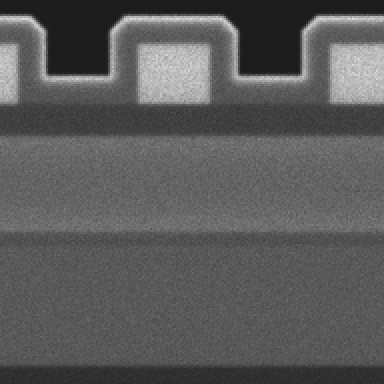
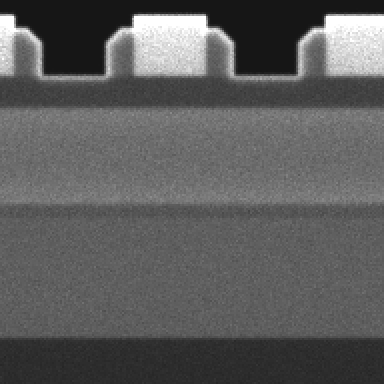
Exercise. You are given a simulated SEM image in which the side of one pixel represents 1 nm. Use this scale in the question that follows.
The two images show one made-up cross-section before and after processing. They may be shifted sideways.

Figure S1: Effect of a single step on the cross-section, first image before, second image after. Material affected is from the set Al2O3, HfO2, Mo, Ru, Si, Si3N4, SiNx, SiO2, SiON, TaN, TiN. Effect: removed SiO2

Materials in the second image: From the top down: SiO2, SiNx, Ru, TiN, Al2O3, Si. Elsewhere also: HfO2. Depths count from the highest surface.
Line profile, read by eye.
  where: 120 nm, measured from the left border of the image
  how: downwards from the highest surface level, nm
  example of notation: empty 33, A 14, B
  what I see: empty 12, SiO2 48, SiNx 32, Ru 96, TiN 14, Al2O3 120, Si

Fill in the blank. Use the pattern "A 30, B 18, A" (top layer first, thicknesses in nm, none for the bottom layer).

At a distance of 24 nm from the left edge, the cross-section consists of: empty 12, SiO2 48, SiNx 32, Ru 96, TiN 14, Al2O3 120, Si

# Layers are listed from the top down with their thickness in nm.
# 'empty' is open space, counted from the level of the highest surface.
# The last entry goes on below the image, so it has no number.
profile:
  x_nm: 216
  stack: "empty 12, SiO2 48, SiNx 32, Ru 96, TiN 14, Al2O3 120, Si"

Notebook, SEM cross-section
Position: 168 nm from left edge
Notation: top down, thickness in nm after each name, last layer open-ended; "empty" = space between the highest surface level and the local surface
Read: HfO2 60, SiNx 32, Ru 96, TiN 14, Al2O3 120, Si